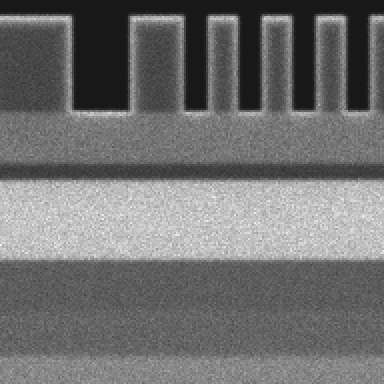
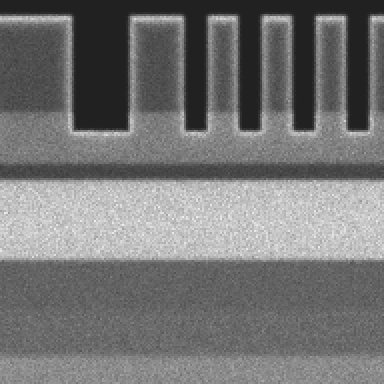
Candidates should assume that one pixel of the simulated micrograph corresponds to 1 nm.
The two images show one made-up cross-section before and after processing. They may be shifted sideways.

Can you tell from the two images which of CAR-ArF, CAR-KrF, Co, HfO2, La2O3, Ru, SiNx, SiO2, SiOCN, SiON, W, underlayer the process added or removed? Yes, it removed Ru.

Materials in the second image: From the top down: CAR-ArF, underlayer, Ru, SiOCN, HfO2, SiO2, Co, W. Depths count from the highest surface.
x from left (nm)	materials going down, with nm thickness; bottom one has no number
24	CAR-ArF 46, underlayer 50, Ru 52, SiOCN 16, HfO2 80, SiO2 50, Co 46, W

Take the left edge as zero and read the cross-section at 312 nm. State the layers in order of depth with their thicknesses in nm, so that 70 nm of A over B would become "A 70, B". empty 116, Ru 32, SiOCN 16, HfO2 80, SiO2 50, Co 46, W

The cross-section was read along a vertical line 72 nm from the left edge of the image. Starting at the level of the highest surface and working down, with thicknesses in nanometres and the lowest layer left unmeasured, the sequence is empty 116, Ru 32, SiOCN 16, HfO2 80, SiO2 50, Co 46, W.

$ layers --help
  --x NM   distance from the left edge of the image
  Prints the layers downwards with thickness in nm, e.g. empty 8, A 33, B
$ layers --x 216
CAR-ArF 46, underlayer 50, Ru 52, SiOCN 16, HfO2 80, SiO2 50, Co 46, W